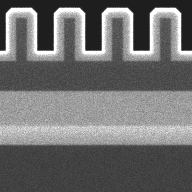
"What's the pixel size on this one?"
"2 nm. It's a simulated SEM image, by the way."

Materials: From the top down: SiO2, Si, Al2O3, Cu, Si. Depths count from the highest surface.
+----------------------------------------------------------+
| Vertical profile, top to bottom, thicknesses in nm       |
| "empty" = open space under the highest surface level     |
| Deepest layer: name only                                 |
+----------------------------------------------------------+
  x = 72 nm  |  empty 10, SiO2 96, Si 60, Al2O3 70, Cu 38, Si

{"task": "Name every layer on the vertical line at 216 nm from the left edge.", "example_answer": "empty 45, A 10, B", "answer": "SiO2 106, Si 60, Al2O3 70, Cu 38, Si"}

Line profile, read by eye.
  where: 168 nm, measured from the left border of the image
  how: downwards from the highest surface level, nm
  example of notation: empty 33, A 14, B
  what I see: empty 10, SiO2 96, Si 60, Al2O3 70, Cu 38, Si